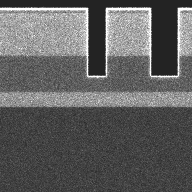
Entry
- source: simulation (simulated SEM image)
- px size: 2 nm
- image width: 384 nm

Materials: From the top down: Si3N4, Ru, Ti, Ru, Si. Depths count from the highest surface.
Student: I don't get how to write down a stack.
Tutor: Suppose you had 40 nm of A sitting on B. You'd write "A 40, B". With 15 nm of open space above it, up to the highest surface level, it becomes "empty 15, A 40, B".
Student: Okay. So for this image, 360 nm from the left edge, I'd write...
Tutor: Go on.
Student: Si3N4 10, Ru 86, Ti 72, Ru 30, Si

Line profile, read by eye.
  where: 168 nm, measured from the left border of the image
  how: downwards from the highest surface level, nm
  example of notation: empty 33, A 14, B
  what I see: Si3N4 10, Ru 86, Ti 72, Ru 30, Si